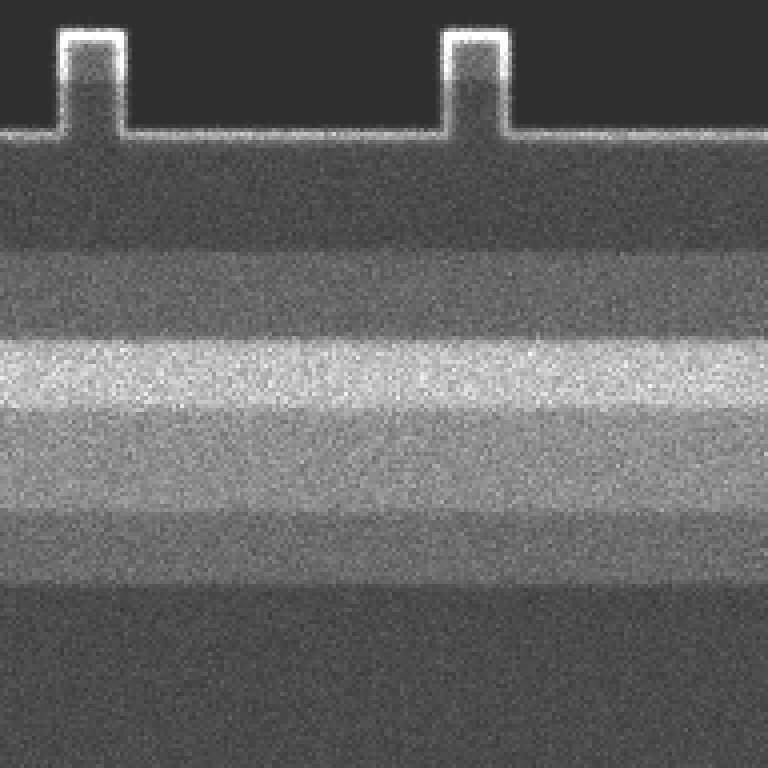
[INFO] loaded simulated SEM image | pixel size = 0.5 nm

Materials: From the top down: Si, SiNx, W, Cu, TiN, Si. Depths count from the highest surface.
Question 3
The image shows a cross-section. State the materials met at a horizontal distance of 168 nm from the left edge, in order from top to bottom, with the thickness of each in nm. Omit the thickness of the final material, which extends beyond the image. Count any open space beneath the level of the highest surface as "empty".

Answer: empty 50, Si 60, SiNx 44, W 34, Cu 52, TiN 36, Si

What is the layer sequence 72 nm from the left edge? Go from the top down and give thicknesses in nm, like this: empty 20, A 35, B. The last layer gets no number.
empty 50, Si 60, SiNx 44, W 34, Cu 52, TiN 36, Si